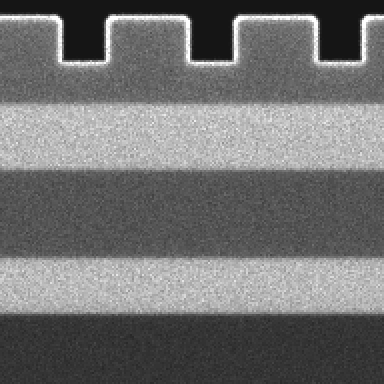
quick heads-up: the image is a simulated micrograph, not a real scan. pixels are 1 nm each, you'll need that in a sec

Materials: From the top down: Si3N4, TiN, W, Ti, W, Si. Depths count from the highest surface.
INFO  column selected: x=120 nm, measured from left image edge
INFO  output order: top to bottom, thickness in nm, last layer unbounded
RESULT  TiN 88, W 66, Ti 88, W 56, Si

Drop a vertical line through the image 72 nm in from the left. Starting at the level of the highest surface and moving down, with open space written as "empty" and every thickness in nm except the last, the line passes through empty 46, TiN 42, W 66, Ti 88, W 56, Si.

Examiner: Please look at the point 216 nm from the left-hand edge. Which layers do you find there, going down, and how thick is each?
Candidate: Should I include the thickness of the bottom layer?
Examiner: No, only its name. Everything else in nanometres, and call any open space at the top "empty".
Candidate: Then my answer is empty 46, TiN 42, W 66, Ti 88, W 56, Si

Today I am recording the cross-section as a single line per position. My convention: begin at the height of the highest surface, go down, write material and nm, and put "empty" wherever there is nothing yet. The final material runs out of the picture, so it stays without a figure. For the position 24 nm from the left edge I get TiN 88, W 66, Ti 88, W 56, Si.